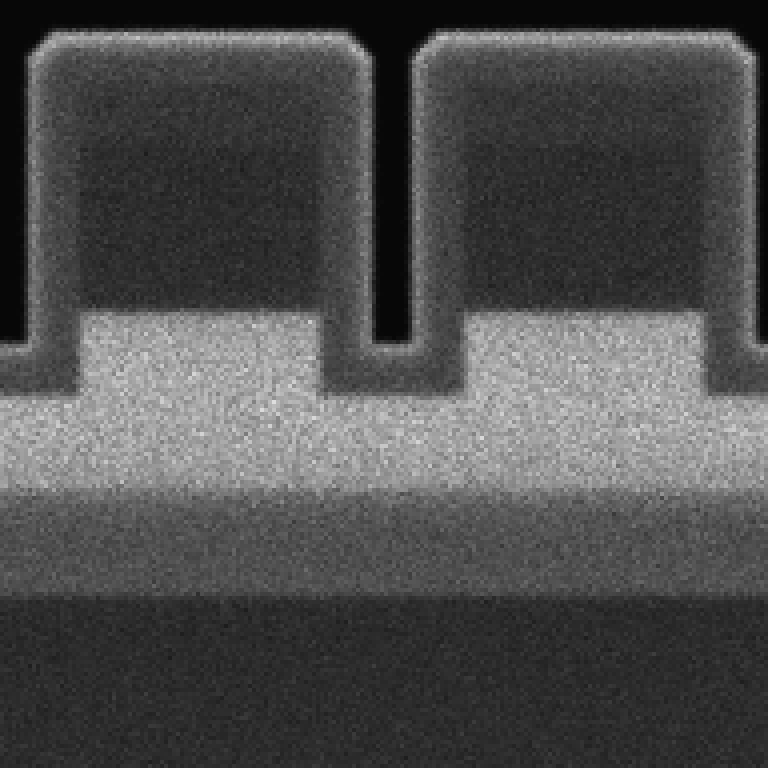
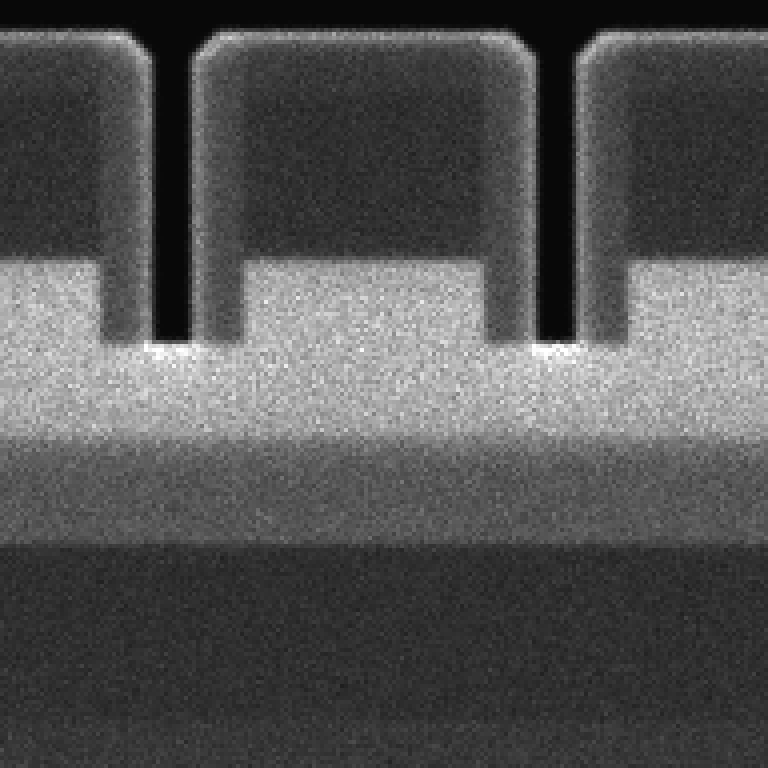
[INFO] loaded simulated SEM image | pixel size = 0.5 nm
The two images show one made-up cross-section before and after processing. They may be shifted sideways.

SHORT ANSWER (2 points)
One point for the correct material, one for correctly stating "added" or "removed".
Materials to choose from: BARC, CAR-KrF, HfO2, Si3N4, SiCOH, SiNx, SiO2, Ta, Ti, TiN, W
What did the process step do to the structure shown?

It removed SiO2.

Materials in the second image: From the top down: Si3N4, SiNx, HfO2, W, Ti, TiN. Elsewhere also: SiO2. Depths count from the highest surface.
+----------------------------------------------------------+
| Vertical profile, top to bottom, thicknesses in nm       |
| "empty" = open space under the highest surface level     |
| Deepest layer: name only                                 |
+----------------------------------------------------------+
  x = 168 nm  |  Si3N4 30, SiNx 84, HfO2 88, W 54, Ti 88, TiN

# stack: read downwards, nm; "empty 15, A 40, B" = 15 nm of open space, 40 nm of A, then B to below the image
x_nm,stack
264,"empty 10, SiO2 146, HfO2 46, W 54, Ti 88, TiN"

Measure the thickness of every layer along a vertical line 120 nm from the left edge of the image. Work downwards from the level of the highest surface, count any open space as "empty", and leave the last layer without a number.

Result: SiO2 156, HfO2 46, W 54, Ti 88, TiN